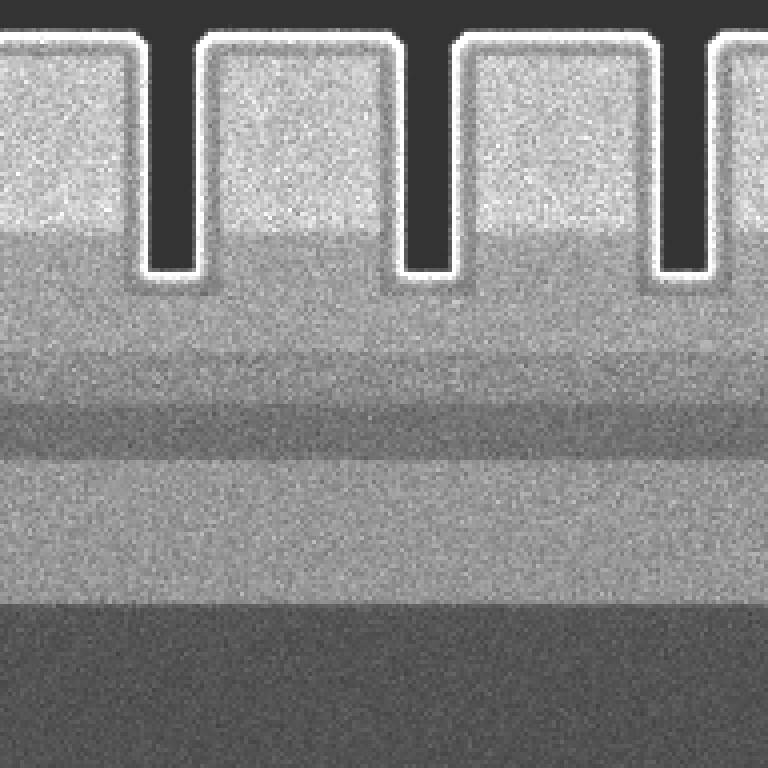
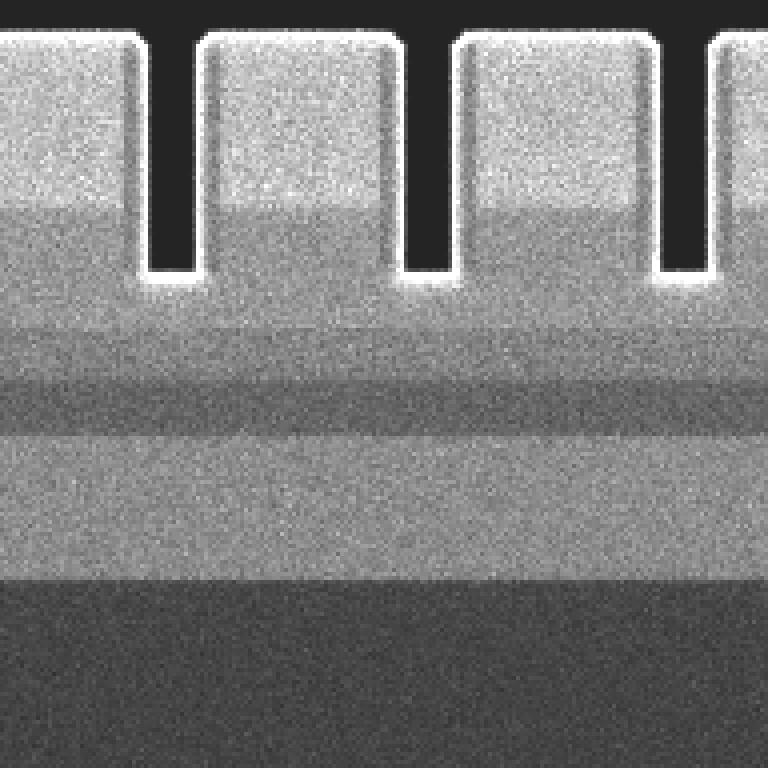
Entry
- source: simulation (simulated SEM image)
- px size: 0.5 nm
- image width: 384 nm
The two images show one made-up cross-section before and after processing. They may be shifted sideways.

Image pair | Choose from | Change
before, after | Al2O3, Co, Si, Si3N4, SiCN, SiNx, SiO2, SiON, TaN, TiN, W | Si3N4 (removed)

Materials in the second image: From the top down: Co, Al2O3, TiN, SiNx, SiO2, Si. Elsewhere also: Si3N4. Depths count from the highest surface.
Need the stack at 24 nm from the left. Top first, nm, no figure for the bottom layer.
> Co 88, Al2O3 60, TiN 26, SiNx 28, SiO2 72, Si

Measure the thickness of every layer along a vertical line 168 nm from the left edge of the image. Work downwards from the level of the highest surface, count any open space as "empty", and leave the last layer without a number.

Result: Co 88, Al2O3 60, TiN 26, SiNx 28, SiO2 72, Si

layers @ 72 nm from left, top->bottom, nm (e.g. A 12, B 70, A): empty 6, Si3N4 114, Al2O3 28, TiN 26, SiNx 28, SiO2 72, Si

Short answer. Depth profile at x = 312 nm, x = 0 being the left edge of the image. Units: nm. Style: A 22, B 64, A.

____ Co 88, Al2O3 60, TiN 26, SiNx 28, SiO2 72, Si